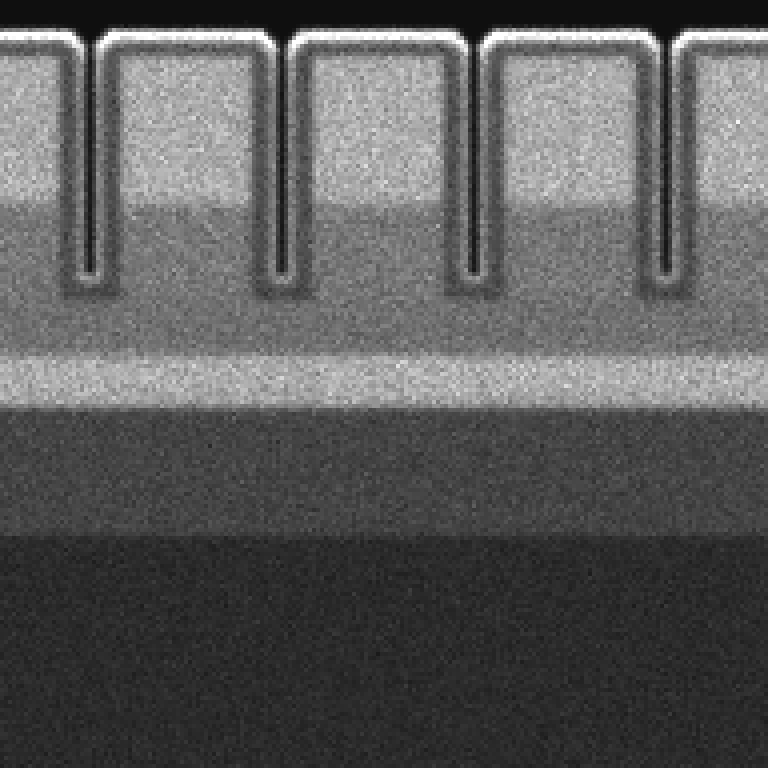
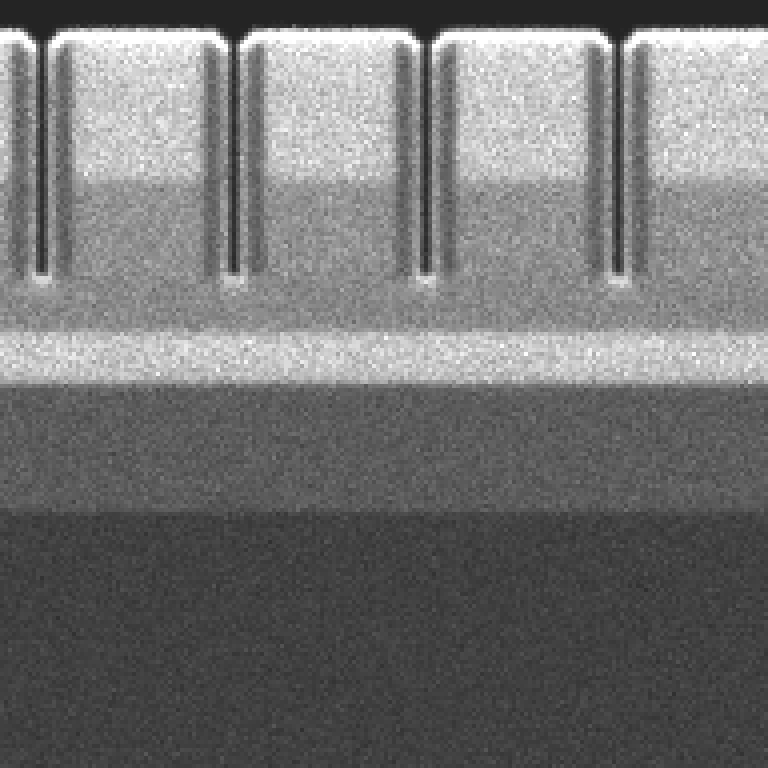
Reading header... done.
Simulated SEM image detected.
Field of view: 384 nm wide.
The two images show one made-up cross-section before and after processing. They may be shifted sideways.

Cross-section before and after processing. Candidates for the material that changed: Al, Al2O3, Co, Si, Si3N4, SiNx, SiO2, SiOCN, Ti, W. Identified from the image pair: SiNx (removed).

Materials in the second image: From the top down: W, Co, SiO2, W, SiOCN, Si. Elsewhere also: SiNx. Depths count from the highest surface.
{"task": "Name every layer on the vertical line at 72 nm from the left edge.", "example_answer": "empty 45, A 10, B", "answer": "W 74, Co 48, SiO2 28, W 26, SiOCN 64, Si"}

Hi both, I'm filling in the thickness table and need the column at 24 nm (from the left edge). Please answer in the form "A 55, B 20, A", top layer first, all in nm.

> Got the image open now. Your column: empty 6, SiNx 116, SiO2 28, W 26, SiOCN 64, Si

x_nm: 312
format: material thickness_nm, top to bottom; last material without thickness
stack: empty 6, SiNx 116, SiO2 28, W 26, SiOCN 64, Si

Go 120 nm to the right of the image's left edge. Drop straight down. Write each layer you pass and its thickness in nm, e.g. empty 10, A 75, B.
empty 6, SiNx 116, SiO2 28, W 26, SiOCN 64, Si